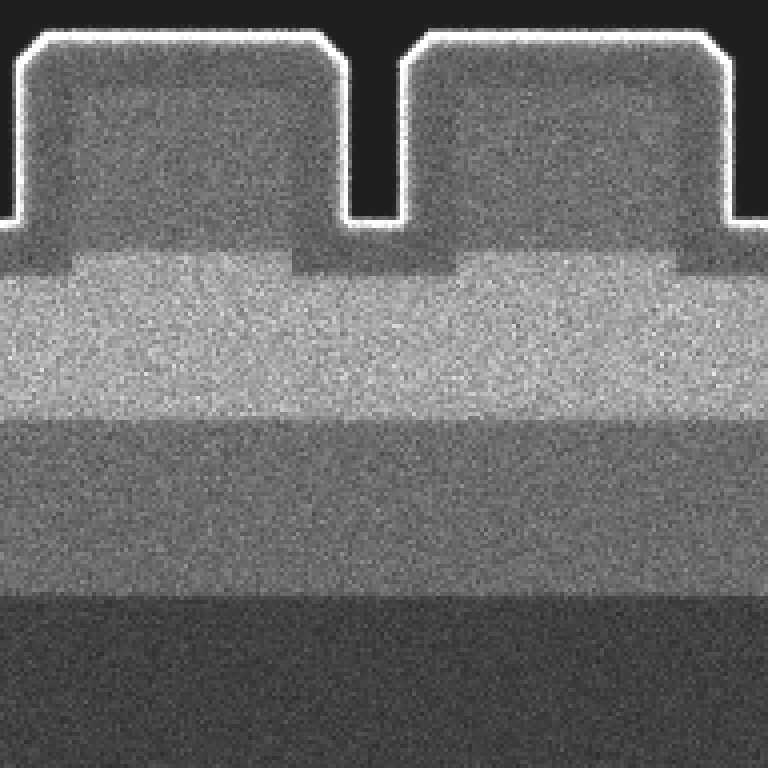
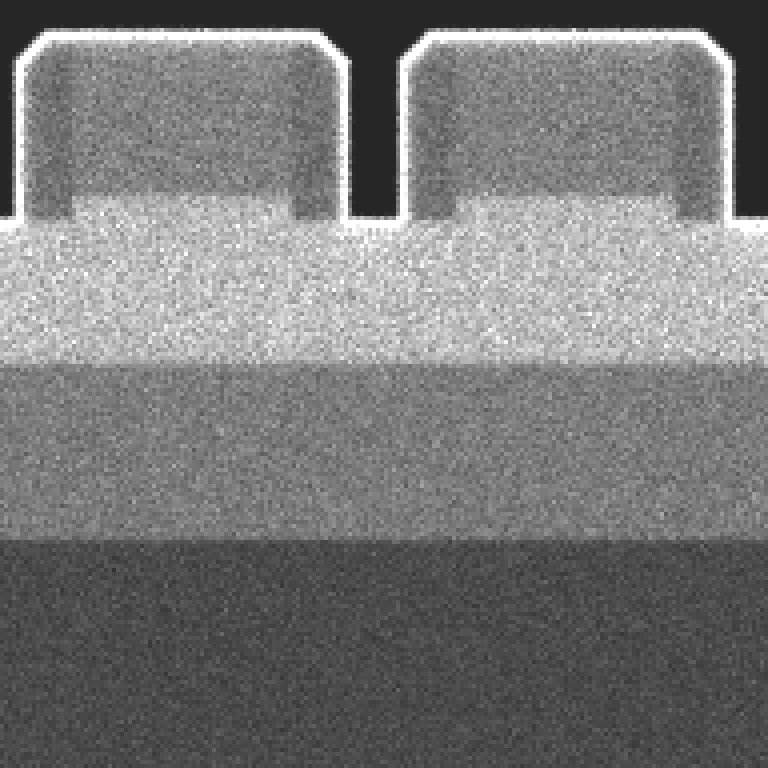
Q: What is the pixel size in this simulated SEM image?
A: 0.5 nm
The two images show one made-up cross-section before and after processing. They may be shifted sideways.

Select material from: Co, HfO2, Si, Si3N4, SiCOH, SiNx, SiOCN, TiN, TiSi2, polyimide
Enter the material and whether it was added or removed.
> SiNx / removed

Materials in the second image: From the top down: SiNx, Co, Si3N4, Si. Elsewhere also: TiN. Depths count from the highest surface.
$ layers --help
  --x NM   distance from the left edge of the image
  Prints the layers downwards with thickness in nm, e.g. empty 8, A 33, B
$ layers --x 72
TiN 82, Co 84, Si3N4 88, Si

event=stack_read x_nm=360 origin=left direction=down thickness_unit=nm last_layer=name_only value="empty 10, SiNx 84, Co 72, Si3N4 88, Si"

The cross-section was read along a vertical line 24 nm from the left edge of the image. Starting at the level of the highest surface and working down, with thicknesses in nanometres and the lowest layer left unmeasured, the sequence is SiNx 94, Co 72, Si3N4 88, Si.